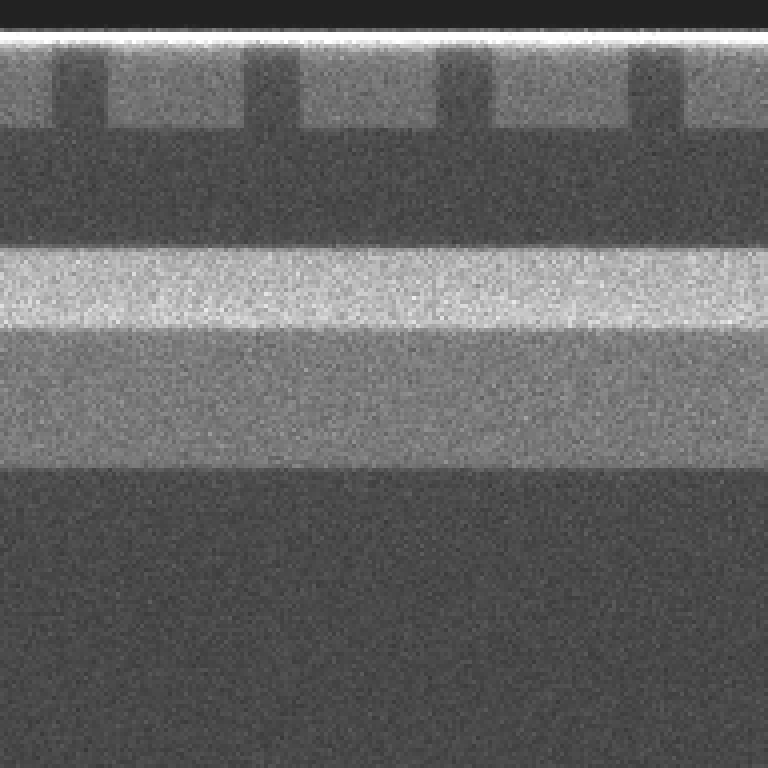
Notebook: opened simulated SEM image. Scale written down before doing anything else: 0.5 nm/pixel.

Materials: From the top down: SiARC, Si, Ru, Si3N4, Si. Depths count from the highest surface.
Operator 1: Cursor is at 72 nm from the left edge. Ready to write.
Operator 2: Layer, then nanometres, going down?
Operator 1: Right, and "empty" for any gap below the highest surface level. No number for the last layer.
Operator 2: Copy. SiARC 48, Si 60, Ru 40, Si3N4 70, Si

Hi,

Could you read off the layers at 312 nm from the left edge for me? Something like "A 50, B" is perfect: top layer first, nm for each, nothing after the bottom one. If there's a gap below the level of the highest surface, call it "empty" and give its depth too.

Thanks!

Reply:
SiARC 48, Si 60, Ru 40, Si3N4 70, Si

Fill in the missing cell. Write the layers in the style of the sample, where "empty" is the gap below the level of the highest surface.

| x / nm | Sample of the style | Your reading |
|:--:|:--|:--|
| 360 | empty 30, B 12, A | SiARC 48, Si 60, Ru 40, Si3N4 70, Si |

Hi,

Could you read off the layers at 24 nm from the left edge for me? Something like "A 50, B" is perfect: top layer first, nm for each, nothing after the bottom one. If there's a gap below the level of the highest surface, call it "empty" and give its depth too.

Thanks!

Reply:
SiARC 48, Si 60, Ru 40, Si3N4 70, Si